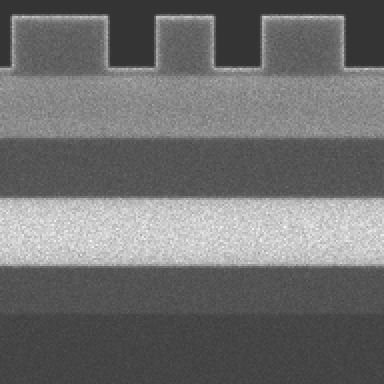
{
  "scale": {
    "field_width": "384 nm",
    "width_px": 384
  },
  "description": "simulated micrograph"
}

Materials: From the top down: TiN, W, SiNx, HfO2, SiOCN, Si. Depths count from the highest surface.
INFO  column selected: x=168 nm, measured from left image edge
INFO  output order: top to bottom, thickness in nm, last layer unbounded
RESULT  TiN 60, W 62, SiNx 60, HfO2 68, SiOCN 48, Si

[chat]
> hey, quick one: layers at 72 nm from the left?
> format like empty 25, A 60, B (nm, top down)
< TiN 60, W 62, SiNx 60, HfO2 68, SiOCN 48, Si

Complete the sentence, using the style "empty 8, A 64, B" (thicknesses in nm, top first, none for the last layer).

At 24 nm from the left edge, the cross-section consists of TiN 60, W 62, SiNx 60, HfO2 68, SiOCN 48, Si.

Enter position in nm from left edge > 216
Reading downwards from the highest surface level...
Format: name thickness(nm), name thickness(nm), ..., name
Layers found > empty 52, TiN 8, W 62, SiNx 60, HfO2 68, SiOCN 48, Si